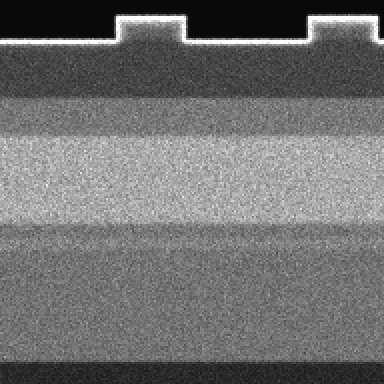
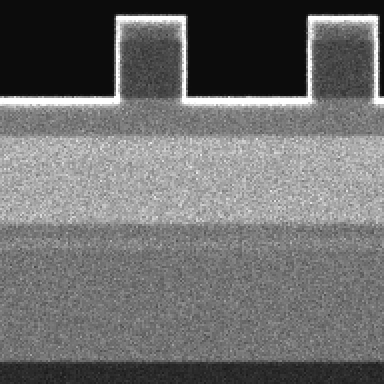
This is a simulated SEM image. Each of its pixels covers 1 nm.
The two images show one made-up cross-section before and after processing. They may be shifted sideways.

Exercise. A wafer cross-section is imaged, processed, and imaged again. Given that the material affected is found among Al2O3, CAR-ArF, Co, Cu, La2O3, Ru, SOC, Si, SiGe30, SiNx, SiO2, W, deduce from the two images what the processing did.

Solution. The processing removed SiNx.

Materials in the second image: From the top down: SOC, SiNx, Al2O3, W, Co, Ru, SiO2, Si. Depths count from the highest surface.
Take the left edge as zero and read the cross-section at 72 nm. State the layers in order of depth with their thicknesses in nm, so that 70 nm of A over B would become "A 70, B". empty 82, Al2O3 38, W 88, Co 14, Ru 12, SiO2 112, Si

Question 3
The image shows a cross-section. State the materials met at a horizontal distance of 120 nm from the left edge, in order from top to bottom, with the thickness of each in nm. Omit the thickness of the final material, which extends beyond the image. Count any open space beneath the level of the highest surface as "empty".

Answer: SOC 24, SiNx 58, Al2O3 38, W 88, Co 14, Ru 12, SiO2 112, Si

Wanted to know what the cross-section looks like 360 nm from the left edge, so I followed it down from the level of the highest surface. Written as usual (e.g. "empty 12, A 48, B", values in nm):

SOC 24, SiNx 58, Al2O3 38, W 88, Co 14, Ru 12, SiO2 112, Si